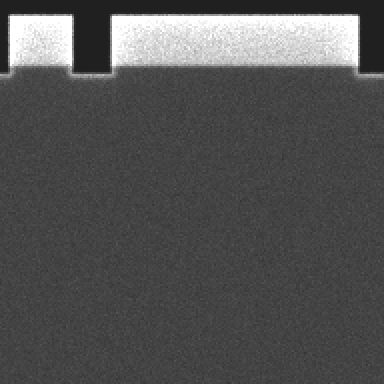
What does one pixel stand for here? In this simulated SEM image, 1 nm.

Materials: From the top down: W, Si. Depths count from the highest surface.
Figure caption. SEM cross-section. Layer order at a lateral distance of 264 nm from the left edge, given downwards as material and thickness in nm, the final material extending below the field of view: W 50, Si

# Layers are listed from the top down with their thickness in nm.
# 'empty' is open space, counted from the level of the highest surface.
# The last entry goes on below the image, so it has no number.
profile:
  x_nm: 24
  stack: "W 50, Si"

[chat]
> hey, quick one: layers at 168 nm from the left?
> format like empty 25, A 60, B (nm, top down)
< W 50, Si